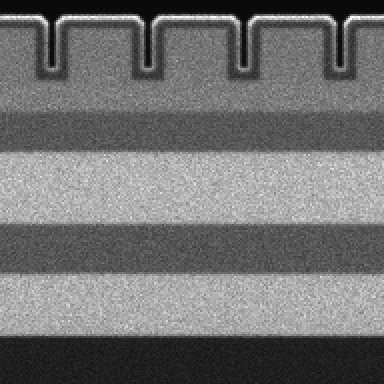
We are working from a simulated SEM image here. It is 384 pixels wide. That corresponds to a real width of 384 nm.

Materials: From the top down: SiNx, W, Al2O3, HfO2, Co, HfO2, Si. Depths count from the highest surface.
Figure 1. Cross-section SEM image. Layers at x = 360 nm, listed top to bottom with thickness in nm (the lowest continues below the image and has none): SiNx 12, W 84, Al2O3 40, HfO2 72, Co 50, HfO2 62, Si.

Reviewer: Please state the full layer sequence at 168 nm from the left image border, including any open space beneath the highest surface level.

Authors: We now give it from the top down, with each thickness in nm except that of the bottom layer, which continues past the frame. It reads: SiNx 12, W 84, Al2O3 40, HfO2 72, Co 50, HfO2 62, Si